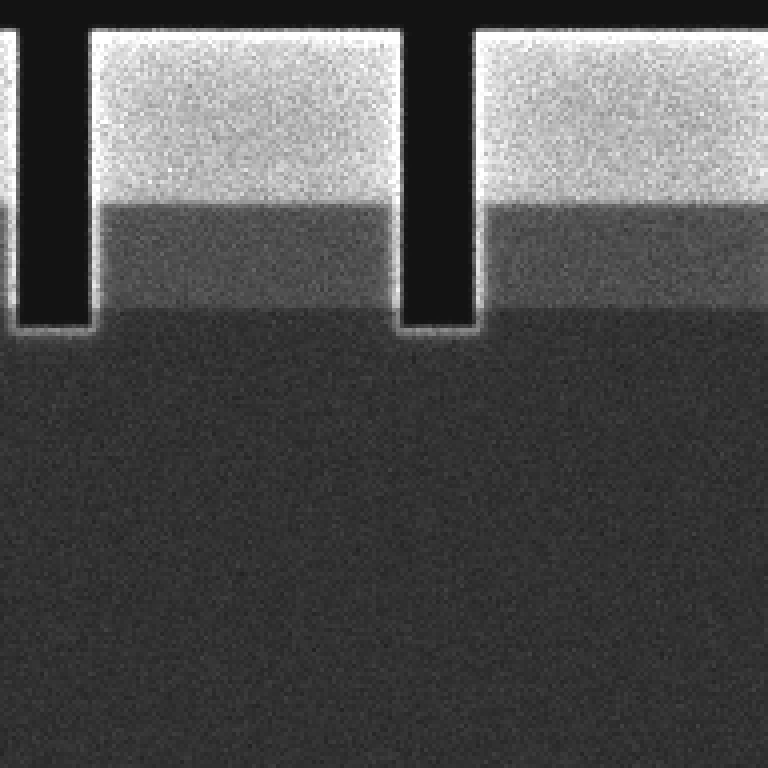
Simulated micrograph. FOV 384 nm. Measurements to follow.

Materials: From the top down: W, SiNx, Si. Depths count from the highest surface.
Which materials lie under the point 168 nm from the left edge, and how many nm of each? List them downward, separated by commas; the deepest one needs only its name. W 86, SiNx 52, Si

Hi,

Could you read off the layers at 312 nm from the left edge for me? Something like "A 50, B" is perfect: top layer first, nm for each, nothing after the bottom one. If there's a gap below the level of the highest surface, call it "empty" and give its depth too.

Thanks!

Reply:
W 86, SiNx 52, Si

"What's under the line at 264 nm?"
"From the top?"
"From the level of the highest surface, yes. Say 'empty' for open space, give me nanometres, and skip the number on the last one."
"W 86, SiNx 52, Si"